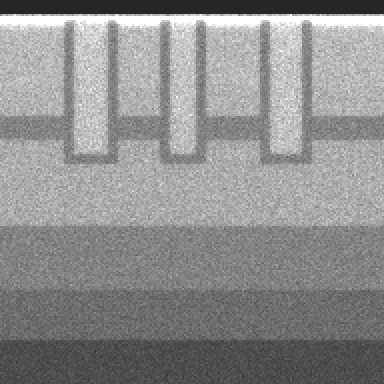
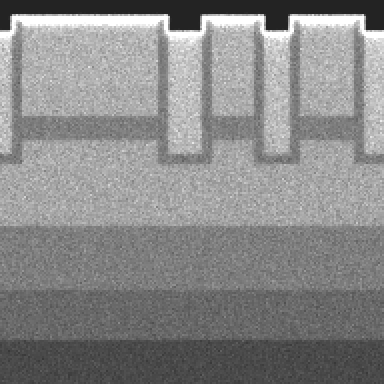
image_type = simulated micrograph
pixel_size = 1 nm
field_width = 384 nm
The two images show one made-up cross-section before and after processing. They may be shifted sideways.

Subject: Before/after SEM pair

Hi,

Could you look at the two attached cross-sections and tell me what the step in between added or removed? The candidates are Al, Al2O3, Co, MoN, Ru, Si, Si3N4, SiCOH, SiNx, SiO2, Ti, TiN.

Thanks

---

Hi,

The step removed Ru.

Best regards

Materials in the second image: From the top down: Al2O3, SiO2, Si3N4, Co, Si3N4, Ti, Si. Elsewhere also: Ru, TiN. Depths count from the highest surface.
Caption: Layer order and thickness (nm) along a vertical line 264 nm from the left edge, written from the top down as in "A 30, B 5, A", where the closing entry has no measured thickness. empty 16, Ru 122, TiN 10, Co 62, Si3N4 64, Ti 50, Si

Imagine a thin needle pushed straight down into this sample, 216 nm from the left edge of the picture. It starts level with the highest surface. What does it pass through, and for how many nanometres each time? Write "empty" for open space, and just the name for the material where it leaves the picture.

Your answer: Al2O3 70, SiO2 30, Si3N4 24, Co 86, Si3N4 64, Ti 50, Si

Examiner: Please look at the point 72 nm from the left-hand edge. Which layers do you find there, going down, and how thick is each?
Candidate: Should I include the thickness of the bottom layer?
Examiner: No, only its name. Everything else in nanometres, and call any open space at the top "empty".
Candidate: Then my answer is Al2O3 70, SiO2 30, Si3N4 24, Co 86, Si3N4 64, Ti 50, Si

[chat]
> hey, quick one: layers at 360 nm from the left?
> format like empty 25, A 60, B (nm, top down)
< TiN 148, Co 62, Si3N4 64, Ti 50, Si